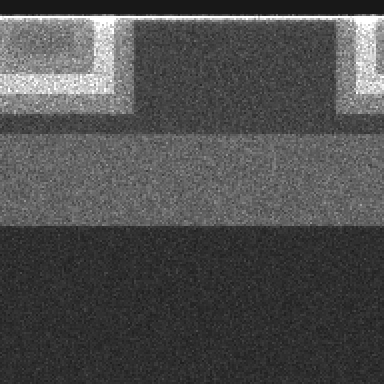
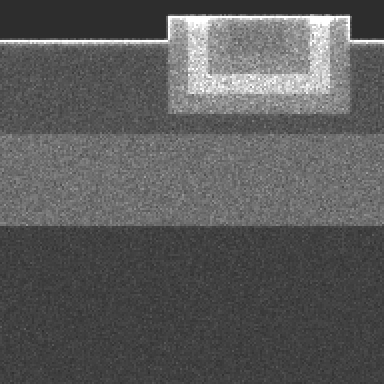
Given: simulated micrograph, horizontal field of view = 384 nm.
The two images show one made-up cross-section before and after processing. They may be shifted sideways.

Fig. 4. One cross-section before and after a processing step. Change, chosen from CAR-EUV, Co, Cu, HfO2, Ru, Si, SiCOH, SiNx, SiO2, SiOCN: SiNx removed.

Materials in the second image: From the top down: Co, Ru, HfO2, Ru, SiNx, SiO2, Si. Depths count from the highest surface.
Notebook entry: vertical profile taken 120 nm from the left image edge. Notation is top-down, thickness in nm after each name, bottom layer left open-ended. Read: empty 24, SiNx 94, SiO2 92, Si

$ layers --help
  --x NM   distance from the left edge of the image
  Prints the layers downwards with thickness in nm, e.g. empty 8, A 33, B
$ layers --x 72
empty 24, SiNx 94, SiO2 92, Si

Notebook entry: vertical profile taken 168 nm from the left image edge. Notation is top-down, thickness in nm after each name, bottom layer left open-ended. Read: Ru 98, SiNx 20, SiO2 92, Si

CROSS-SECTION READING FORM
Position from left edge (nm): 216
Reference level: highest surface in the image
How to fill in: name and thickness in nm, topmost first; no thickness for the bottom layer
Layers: Ru 58, HfO2 20, Ru 20, SiNx 20, SiO2 92, Si